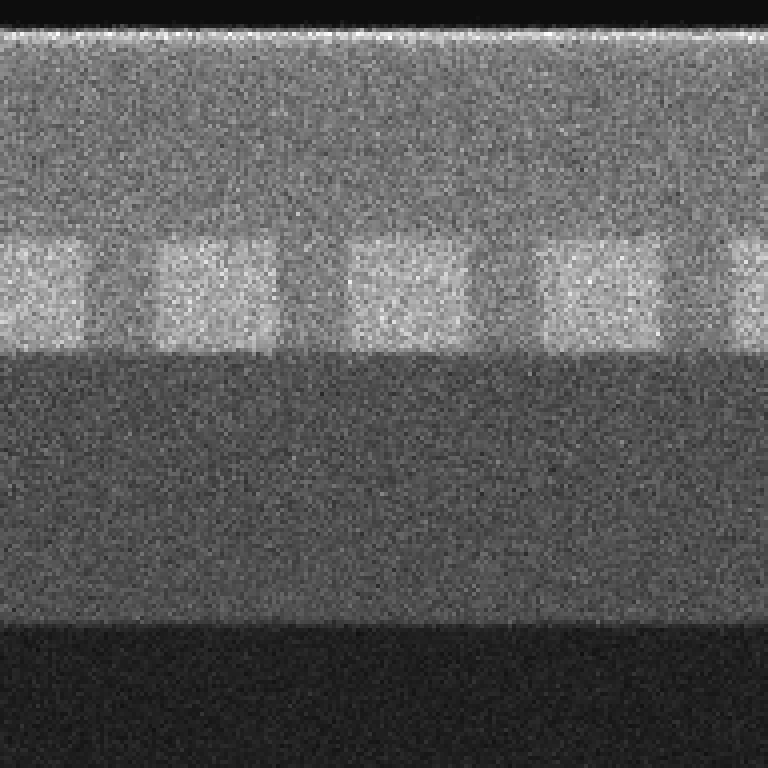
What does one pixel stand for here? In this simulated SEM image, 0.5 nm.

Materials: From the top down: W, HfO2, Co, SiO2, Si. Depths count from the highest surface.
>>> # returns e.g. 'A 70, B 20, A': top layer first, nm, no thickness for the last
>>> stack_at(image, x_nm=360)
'W 160, Co 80, SiO2 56, Si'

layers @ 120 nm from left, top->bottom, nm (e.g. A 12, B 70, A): W 104, HfO2 56, Co 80, SiO2 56, Si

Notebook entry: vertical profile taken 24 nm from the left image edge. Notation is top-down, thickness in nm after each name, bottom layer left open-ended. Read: W 104, HfO2 56, Co 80, SiO2 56, Si